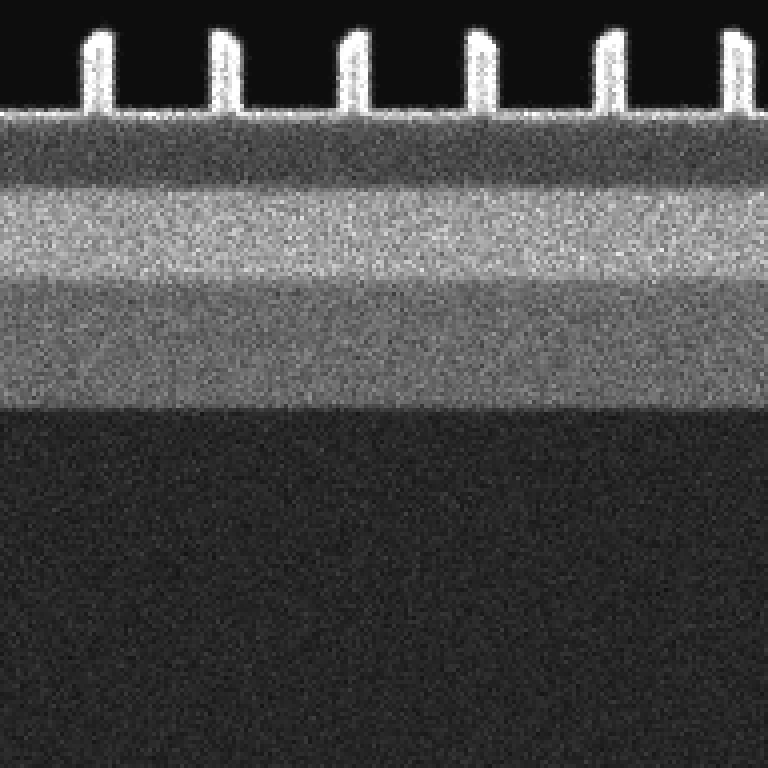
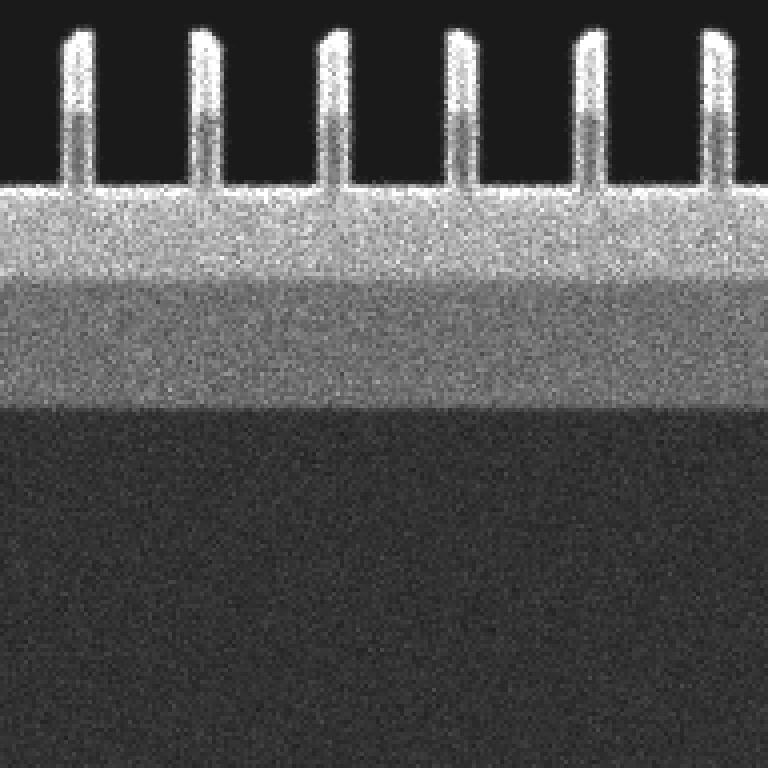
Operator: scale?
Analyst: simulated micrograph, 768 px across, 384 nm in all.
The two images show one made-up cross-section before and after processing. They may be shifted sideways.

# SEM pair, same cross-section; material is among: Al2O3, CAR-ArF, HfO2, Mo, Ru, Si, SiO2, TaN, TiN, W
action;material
removed;TiN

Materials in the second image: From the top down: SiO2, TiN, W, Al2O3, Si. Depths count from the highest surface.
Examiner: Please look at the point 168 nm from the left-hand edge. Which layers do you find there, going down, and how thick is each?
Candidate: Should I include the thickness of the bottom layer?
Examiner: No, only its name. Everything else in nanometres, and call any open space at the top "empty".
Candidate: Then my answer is SiO2 40, TiN 38, W 46, Al2O3 64, Si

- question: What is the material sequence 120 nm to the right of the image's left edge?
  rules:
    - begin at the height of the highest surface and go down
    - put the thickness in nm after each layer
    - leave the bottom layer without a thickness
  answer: empty 78, W 46, Al2O3 64, Si